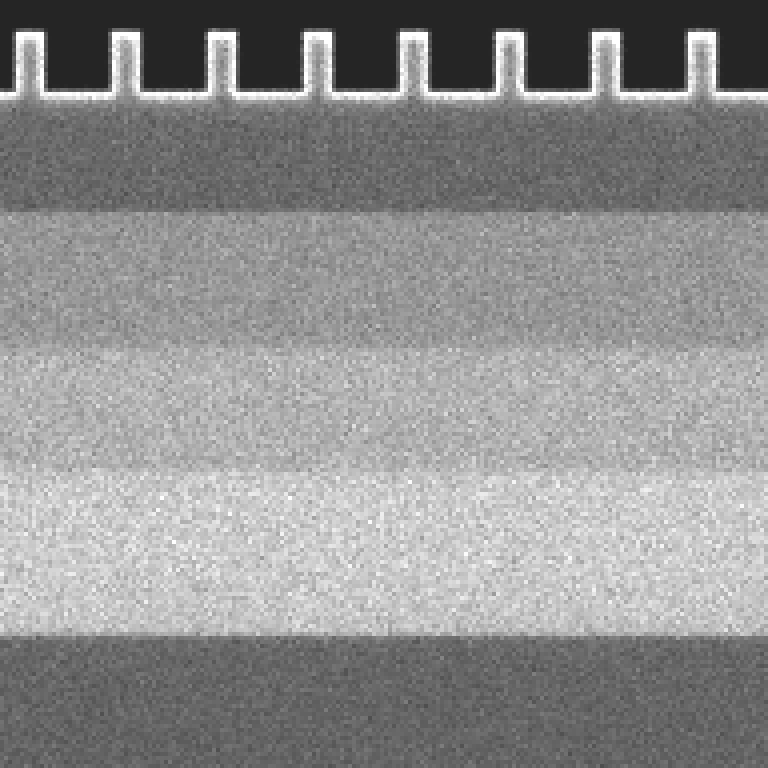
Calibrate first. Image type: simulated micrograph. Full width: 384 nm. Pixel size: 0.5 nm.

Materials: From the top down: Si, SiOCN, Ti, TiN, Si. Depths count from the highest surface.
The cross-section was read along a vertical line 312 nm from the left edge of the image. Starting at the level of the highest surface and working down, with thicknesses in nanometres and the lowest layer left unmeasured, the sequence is empty 30, Si 60, SiOCN 68, Ti 62, TiN 82, Si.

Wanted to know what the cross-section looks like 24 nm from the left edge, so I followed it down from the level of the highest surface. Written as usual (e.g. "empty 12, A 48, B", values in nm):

empty 30, Si 60, SiOCN 68, Ti 62, TiN 82, Si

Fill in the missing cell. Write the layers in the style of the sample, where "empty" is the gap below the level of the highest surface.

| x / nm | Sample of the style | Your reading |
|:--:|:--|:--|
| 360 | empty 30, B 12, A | empty 30, Si 60, SiOCN 68, Ti 62, TiN 82, Si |